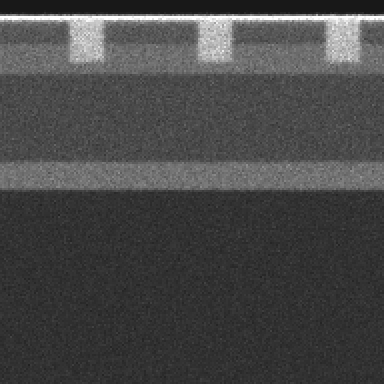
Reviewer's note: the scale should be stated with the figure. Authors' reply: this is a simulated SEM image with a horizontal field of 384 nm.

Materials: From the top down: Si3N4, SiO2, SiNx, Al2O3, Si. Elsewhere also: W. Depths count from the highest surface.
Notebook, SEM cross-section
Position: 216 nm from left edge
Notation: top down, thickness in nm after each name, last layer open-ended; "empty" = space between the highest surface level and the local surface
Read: W 46, SiO2 12, SiNx 88, Al2O3 28, Si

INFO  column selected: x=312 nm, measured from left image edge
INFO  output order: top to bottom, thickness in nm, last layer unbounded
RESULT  Si3N4 28, SiO2 30, SiNx 88, Al2O3 28, Si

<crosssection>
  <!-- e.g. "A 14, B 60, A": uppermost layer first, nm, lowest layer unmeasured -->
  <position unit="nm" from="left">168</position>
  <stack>Si3N4 28, SiO2 30, SiNx 88, Al2O3 28, Si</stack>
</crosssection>